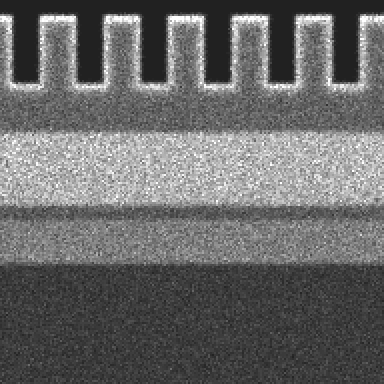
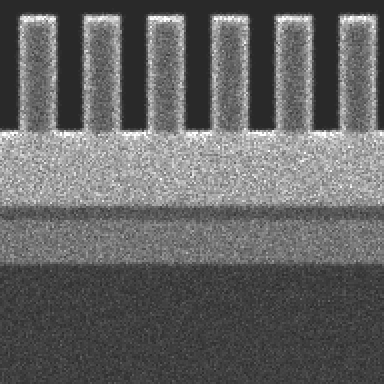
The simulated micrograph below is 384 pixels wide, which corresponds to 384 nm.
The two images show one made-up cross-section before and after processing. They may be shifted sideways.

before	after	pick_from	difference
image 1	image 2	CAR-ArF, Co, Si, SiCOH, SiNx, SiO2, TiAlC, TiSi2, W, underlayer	underlayer removed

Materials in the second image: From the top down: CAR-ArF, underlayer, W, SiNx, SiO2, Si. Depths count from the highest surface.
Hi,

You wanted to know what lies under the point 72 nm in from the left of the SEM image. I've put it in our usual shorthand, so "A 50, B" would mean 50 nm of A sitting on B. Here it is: empty 116, W 74, SiNx 14, SiO2 44, Si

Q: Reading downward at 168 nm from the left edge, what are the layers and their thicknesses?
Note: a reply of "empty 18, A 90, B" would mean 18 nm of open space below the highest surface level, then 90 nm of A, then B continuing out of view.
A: CAR-ArF 68, underlayer 48, W 74, SiNx 14, SiO2 44, Si